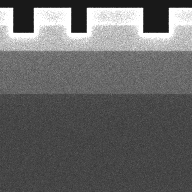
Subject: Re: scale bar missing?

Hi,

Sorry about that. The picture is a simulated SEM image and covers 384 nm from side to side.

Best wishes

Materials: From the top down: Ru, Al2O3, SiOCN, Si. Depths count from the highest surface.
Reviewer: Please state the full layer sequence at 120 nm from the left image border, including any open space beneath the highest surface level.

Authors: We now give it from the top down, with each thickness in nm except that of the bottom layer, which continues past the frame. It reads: Ru 34, Al2O3 52, SiOCN 86, Si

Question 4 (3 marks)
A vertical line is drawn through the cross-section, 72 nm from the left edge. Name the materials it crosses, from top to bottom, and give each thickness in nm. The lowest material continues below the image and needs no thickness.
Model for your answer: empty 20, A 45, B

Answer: Ru 34, Al2O3 52, SiOCN 86, Si